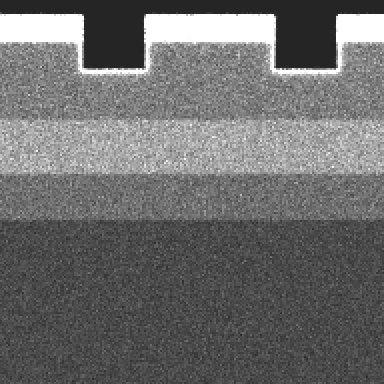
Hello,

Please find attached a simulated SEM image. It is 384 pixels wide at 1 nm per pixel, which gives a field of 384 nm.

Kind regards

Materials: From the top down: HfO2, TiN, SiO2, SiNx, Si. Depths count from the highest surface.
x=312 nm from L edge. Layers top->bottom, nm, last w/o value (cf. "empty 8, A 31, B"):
empty 54, TiN 50, SiO2 54, SiNx 46, Si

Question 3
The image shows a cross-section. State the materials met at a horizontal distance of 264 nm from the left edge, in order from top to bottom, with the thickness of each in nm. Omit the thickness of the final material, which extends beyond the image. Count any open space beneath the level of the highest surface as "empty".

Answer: HfO2 26, TiN 78, SiO2 54, SiNx 46, Si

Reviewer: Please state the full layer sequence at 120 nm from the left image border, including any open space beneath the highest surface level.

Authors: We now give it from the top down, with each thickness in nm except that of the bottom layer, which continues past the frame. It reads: empty 54, TiN 50, SiO2 54, SiNx 46, Si